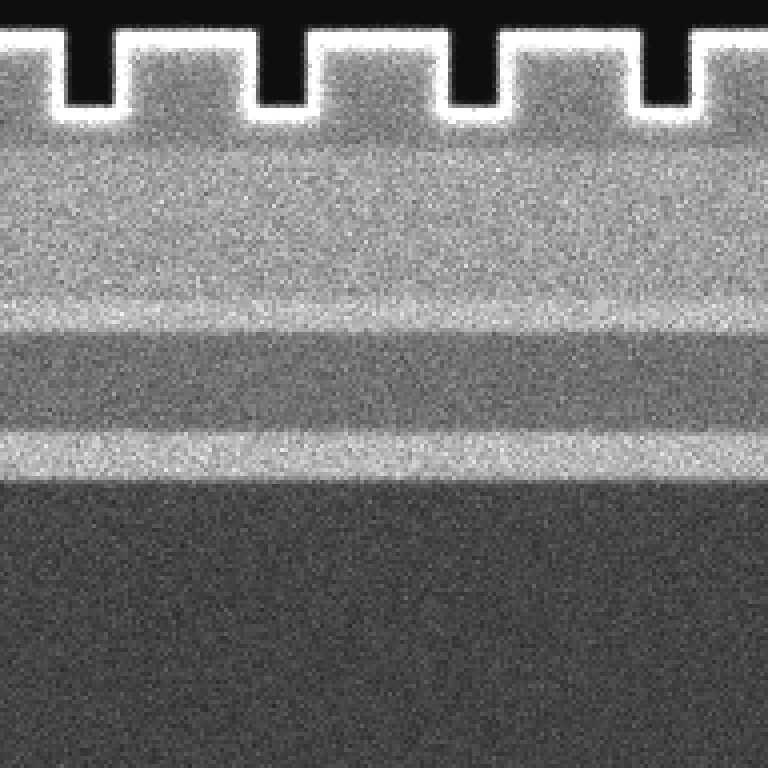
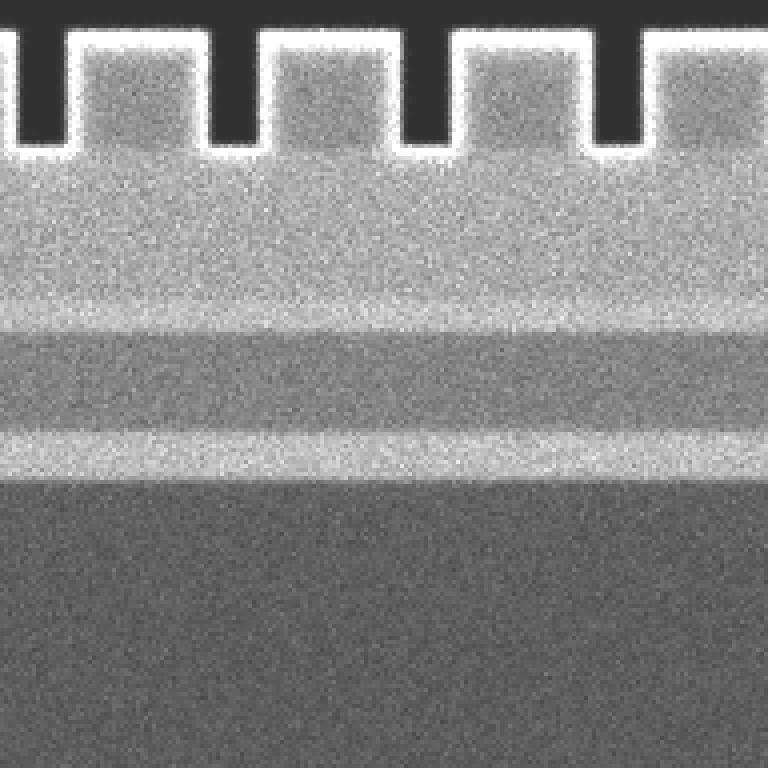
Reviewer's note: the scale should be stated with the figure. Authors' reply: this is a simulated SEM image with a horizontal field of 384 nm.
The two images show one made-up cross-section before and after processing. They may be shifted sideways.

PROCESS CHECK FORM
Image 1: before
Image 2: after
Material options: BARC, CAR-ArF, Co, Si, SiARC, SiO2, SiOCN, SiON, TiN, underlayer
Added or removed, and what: removed, underlayer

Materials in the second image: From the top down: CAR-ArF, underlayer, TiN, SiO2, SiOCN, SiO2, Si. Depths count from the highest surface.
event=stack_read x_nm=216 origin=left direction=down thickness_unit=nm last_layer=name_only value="empty 58, TiN 76, SiO2 16, SiOCN 50, SiO2 24, Si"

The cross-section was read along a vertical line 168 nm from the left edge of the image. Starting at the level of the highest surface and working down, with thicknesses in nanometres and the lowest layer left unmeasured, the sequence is CAR-ArF 38, underlayer 20, TiN 76, SiO2 16, SiOCN 50, SiO2 24, Si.